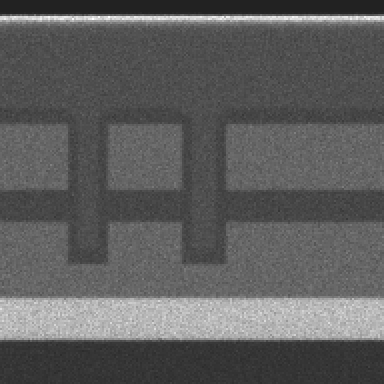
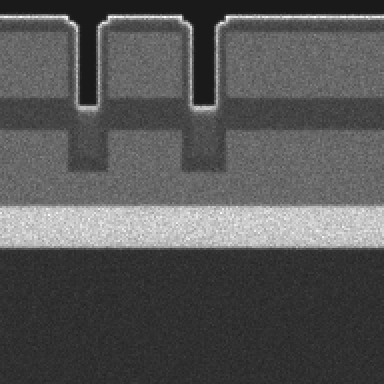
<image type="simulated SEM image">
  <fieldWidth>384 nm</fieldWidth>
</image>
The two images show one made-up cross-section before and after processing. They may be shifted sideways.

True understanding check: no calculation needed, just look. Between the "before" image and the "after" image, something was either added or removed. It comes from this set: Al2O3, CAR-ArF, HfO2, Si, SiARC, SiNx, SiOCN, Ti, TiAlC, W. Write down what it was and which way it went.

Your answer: SiARC (removed)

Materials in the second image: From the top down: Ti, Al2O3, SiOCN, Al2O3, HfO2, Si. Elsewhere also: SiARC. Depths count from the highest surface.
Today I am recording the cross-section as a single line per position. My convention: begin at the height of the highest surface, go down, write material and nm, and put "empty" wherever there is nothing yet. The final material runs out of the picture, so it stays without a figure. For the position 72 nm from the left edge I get empty 6, Ti 150, Al2O3 34, HfO2 42, Si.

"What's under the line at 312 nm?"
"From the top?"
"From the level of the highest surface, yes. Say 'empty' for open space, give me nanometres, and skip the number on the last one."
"Ti 16, Al2O3 66, SiOCN 32, Al2O3 76, HfO2 42, Si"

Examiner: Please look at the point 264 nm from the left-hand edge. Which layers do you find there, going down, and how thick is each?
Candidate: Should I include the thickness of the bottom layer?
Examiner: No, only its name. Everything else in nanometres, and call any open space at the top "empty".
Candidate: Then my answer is Ti 16, Al2O3 66, SiOCN 32, Al2O3 76, HfO2 42, Si